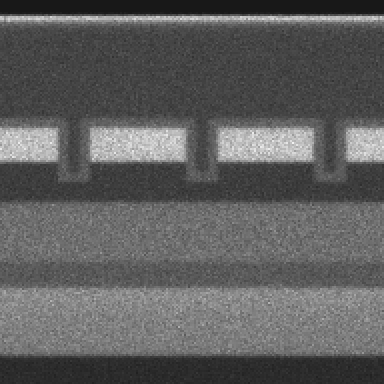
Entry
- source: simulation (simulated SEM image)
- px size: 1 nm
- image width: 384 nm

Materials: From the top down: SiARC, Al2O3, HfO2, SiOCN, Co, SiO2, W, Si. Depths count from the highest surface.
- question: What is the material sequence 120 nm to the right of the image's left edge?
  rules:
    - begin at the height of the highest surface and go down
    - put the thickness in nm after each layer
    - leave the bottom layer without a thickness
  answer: SiARC 102, Al2O3 10, HfO2 34, SiOCN 40, Co 60, SiO2 26, W 68, Si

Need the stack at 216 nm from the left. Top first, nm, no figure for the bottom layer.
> SiARC 102, Al2O3 64, SiOCN 20, Co 60, SiO2 26, W 68, Si